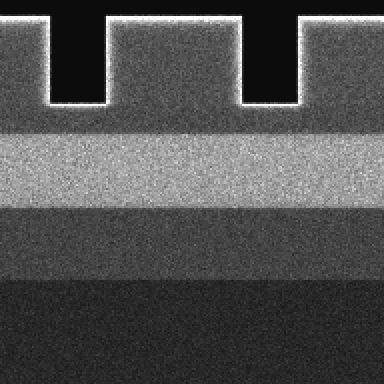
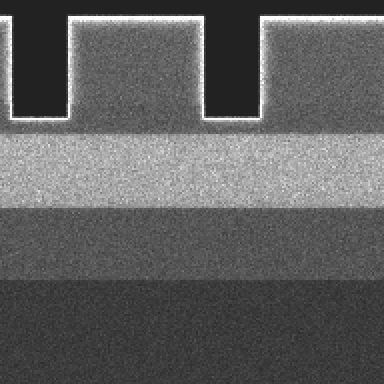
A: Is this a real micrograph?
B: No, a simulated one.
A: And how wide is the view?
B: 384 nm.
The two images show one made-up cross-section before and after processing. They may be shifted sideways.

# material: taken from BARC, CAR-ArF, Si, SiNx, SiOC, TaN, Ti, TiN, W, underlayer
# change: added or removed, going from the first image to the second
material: TiN
change: removed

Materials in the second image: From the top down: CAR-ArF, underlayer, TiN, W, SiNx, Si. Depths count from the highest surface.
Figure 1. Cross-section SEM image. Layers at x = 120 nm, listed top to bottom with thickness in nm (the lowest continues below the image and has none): CAR-ArF 48, underlayer 40, TiN 30, W 74, SiNx 72, Si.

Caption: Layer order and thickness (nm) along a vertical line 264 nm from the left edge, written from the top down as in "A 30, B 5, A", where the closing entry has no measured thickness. CAR-ArF 48, underlayer 40, TiN 30, W 74, SiNx 72, Si